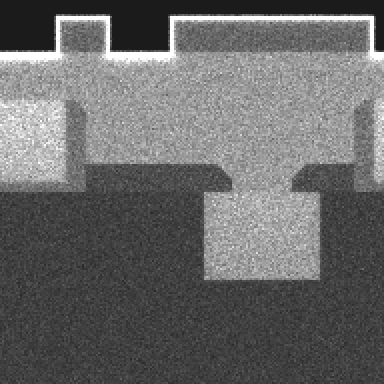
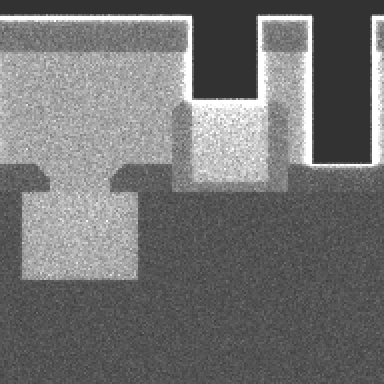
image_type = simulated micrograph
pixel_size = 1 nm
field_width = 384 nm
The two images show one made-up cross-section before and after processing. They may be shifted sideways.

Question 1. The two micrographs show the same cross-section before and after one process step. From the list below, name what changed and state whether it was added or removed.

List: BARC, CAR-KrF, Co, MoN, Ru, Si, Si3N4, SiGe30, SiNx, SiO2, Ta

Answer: SiO2, removed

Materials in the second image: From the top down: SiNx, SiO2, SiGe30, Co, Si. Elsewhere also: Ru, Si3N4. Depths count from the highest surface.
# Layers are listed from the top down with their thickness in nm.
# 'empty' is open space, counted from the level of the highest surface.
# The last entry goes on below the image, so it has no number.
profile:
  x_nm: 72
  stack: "SiNx 36, SiO2 140, Co 88, Si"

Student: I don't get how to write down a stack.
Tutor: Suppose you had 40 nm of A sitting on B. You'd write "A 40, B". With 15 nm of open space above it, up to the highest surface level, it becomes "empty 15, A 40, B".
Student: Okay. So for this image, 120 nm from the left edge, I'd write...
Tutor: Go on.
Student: SiNx 36, SiO2 116, SiGe30 24, Co 88, Si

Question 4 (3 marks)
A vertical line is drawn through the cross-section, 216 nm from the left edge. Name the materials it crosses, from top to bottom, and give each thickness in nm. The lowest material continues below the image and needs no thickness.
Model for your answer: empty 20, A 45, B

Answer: empty 84, Ru 82, Si3N4 10, Si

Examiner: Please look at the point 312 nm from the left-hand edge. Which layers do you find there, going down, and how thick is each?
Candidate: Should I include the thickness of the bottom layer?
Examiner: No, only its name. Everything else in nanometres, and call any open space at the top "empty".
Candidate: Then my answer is empty 148, SiGe30 28, Si